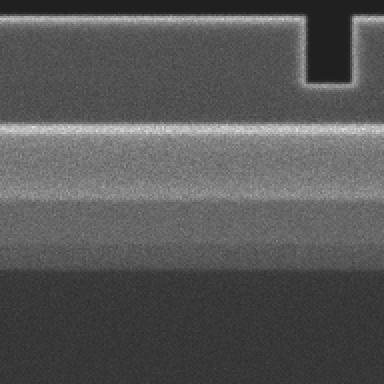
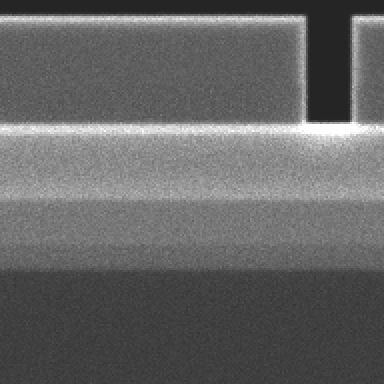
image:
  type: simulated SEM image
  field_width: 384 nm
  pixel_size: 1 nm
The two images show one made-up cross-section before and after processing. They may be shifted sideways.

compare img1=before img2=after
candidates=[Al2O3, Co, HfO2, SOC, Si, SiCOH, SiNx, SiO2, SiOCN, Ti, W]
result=removed:SiNx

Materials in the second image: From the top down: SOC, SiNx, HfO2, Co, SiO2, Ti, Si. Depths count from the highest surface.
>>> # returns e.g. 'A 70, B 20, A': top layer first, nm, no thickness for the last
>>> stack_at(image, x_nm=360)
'SOC 68, SiNx 40, HfO2 10, Co 66, SiO2 44, Ti 26, Si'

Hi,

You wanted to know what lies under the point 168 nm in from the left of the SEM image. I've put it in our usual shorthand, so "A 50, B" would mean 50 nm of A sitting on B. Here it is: SOC 68, SiNx 40, HfO2 10, Co 66, SiO2 44, Ti 26, Si